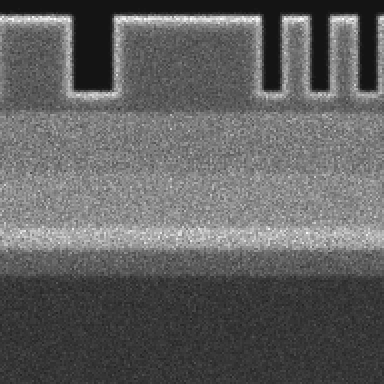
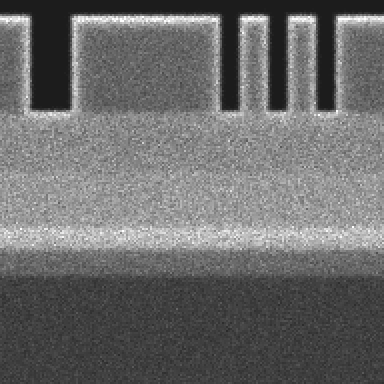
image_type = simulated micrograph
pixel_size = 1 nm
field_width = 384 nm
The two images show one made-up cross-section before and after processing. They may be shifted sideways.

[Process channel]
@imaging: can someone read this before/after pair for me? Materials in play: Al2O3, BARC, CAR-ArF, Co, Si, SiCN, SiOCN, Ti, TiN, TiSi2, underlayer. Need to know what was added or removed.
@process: underlayer removed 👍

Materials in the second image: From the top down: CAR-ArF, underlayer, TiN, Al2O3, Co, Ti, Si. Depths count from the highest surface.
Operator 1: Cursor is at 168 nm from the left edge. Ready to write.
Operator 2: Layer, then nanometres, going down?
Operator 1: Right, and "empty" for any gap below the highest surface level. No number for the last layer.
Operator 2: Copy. CAR-ArF 76, underlayer 20, TiN 62, Al2O3 54, Co 22, Ti 26, Si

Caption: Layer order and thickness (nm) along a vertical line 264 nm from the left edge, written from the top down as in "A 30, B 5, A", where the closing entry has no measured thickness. CAR-ArF 76, underlayer 20, TiN 62, Al2O3 54, Co 22, Ti 26, Si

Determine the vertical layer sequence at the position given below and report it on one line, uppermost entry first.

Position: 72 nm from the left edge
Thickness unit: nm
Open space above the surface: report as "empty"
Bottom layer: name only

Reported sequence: CAR-ArF 76, underlayer 20, TiN 62, Al2O3 54, Co 22, Ti 26, Si